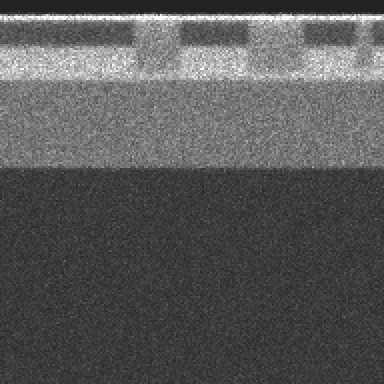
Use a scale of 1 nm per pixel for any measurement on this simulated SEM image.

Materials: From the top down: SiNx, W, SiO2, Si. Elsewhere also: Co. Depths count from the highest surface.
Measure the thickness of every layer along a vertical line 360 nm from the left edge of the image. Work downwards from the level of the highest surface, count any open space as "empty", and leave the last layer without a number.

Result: Co 56, W 8, SiO2 88, Si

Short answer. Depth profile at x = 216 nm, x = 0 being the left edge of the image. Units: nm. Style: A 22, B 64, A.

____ SiNx 30, W 34, SiO2 88, Si